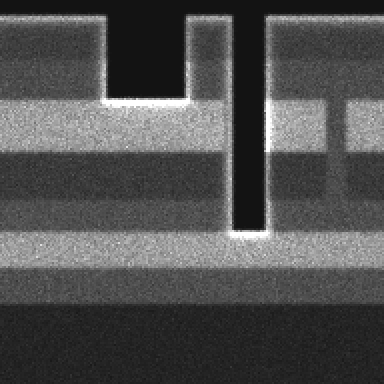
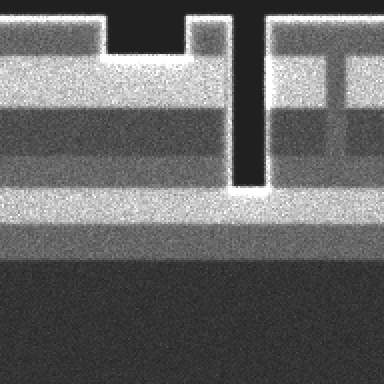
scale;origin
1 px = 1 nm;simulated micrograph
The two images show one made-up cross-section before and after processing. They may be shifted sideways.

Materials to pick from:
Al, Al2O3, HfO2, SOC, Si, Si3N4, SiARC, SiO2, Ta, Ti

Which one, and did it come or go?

SOC - removed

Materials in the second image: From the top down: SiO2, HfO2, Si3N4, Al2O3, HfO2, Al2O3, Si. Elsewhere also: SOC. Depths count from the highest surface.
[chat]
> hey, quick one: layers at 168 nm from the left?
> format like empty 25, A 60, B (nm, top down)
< empty 40, HfO2 52, Si3N4 48, Al2O3 32, HfO2 36, Al2O3 36, Si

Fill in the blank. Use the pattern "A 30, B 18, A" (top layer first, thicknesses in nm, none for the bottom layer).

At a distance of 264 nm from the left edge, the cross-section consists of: empty 172, HfO2 36, Al2O3 36, Si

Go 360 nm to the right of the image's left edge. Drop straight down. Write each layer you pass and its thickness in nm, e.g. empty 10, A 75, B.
SiO2 40, HfO2 52, Si3N4 48, Al2O3 32, HfO2 36, Al2O3 36, Si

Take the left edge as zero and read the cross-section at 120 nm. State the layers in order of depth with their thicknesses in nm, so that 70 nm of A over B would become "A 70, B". empty 40, HfO2 52, Si3N4 48, Al2O3 32, HfO2 36, Al2O3 36, Si